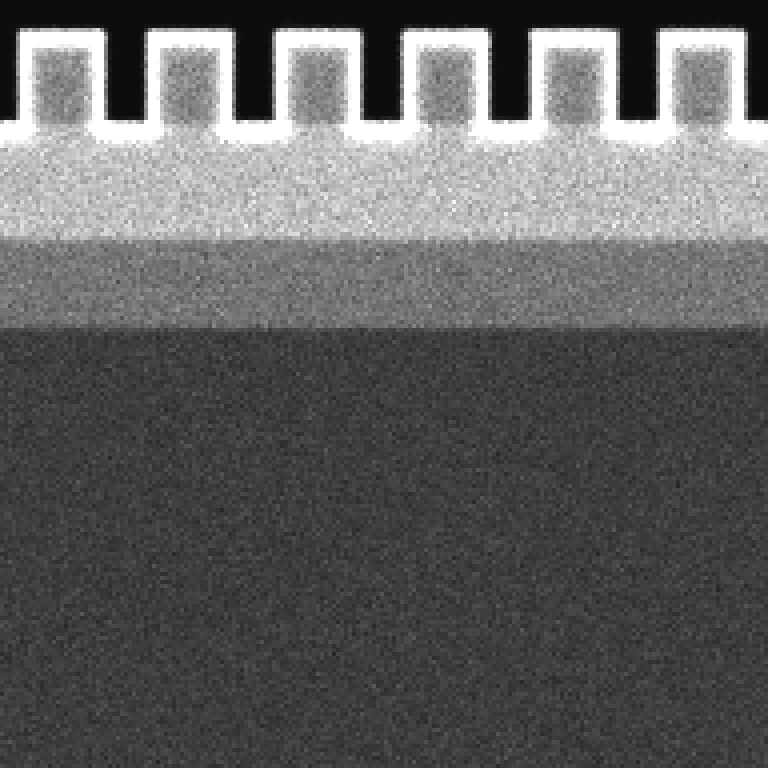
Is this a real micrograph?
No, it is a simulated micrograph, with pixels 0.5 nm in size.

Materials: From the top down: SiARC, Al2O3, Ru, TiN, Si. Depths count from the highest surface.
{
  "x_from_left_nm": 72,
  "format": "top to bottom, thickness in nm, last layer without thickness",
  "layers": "empty 46, Al2O3 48, Ru 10, TiN 44, Si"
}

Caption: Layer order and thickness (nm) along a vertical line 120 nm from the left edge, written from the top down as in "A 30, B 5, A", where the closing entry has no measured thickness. empty 46, Al2O3 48, Ru 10, TiN 44, Si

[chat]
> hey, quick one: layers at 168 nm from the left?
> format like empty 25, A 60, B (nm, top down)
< SiARC 46, Al2O3 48, Ru 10, TiN 44, Si